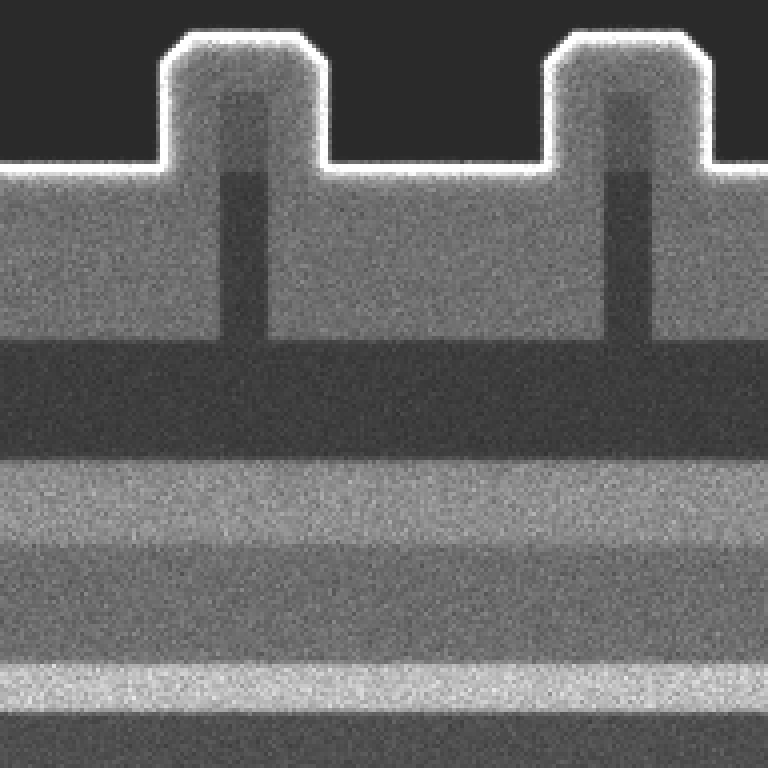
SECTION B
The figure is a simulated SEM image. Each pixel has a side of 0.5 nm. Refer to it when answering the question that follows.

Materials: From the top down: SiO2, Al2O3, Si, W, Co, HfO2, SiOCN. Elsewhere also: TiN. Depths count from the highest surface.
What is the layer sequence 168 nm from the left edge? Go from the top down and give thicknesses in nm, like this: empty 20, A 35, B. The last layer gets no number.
empty 66, SiO2 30, Al2O3 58, Si 60, W 42, Co 60, HfO2 24, SiOCN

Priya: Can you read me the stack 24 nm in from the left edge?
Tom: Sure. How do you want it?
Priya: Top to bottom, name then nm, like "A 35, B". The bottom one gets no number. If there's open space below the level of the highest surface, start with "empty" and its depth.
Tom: empty 66, SiO2 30, Al2O3 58, Si 60, W 42, Co 60, HfO2 24, SiOCN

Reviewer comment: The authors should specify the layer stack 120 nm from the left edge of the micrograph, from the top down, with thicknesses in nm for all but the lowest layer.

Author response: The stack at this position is SiO2 30, TiN 40, Si 144, W 42, Co 60, HfO2 24, SiOCN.